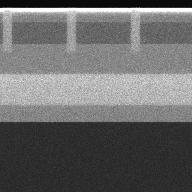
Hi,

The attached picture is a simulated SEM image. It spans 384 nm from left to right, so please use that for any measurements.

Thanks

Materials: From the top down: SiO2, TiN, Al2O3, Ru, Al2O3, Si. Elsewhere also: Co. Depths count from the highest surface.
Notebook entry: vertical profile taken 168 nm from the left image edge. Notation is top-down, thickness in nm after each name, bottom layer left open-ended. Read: SiO2 28, TiN 44, Al2O3 60, Ru 62, Al2O3 34, Si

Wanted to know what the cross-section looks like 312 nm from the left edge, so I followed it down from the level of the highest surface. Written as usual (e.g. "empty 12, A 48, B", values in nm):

SiO2 28, TiN 44, Al2O3 60, Ru 62, Al2O3 34, Si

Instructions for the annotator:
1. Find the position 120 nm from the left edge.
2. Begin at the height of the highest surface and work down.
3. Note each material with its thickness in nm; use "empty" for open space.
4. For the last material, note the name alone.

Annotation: SiO2 28, TiN 44, Al2O3 60, Ru 62, Al2O3 34, Si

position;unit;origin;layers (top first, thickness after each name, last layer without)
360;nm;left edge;SiO2 28, TiN 44, Al2O3 60, Ru 62, Al2O3 34, Si